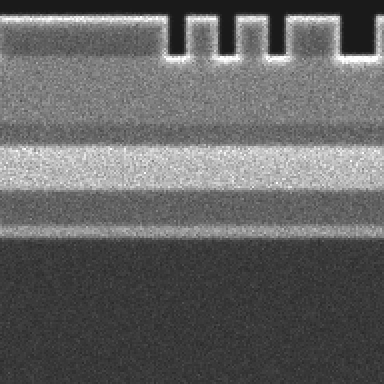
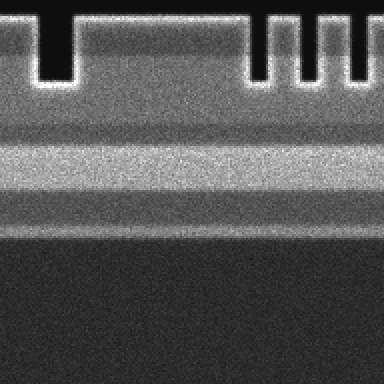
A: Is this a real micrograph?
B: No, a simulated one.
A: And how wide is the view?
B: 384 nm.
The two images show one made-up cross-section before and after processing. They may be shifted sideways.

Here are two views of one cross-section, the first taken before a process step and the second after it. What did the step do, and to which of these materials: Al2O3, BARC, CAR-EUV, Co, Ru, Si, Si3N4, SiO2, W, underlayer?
It removed SiO2.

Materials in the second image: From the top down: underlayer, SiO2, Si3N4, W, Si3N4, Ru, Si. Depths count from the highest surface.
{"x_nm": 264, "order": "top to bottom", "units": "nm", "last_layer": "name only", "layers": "empty 66, SiO2 42, Si3N4 22, W 44, Si3N4 36, Ru 12, Si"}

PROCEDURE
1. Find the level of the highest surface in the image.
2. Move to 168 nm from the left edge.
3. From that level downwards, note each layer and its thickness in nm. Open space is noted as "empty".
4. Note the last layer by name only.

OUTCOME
underlayer 40, SiO2 68, Si3N4 22, W 44, Si3N4 36, Ru 12, Si